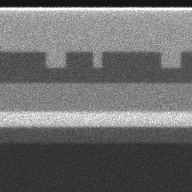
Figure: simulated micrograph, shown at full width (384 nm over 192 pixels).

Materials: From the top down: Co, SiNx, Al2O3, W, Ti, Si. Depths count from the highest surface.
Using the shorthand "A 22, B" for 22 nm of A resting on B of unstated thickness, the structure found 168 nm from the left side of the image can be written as Co 88, SiNx 62, Al2O3 58, W 30, Ti 32, Si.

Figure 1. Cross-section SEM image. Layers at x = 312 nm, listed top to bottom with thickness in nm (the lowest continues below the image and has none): Co 88, SiNx 62, Al2O3 58, W 30, Ti 32, Si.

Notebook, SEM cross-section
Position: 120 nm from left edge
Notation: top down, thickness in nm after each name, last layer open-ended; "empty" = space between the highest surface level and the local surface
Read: Co 120, SiNx 30, Al2O3 58, W 30, Ti 32, Si